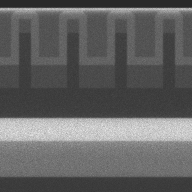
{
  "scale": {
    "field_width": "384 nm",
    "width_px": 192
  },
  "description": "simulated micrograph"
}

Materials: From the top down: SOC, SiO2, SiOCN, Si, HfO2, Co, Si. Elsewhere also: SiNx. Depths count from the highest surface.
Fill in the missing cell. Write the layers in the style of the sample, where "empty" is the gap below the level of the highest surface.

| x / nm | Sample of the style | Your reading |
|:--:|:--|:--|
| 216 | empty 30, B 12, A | SOC 12, SiO2 102, SiOCN 46, Si 60, HfO2 46, Co 72, Si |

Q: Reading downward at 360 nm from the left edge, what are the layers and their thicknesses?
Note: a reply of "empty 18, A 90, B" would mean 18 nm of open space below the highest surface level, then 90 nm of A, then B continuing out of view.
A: SOC 10, SiO2 104, SiOCN 46, Si 60, HfO2 46, Co 72, Si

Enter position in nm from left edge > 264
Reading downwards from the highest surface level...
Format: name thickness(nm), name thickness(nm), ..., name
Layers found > SOC 10, SiO2 104, SiOCN 46, Si 60, HfO2 46, Co 72, Si